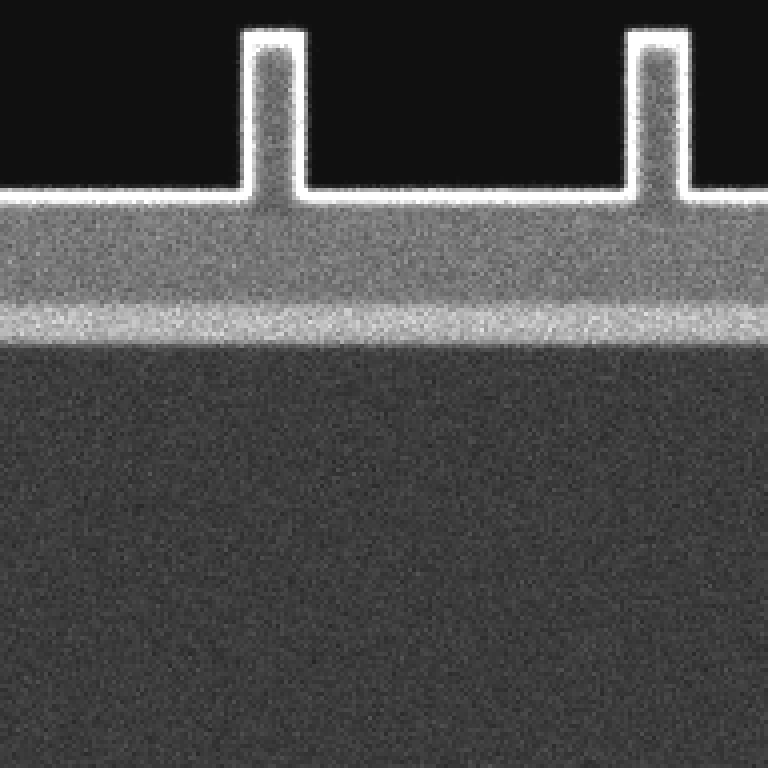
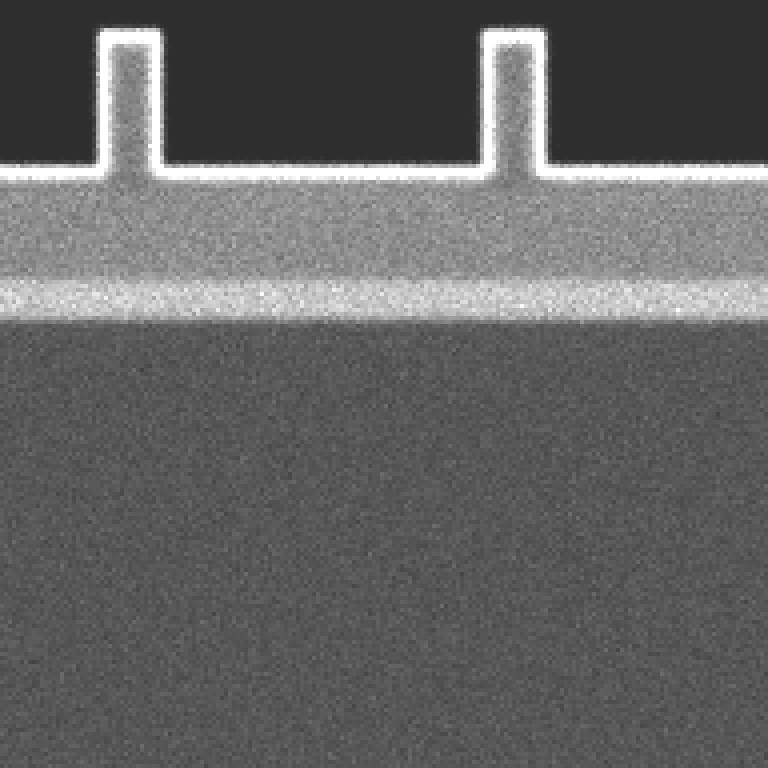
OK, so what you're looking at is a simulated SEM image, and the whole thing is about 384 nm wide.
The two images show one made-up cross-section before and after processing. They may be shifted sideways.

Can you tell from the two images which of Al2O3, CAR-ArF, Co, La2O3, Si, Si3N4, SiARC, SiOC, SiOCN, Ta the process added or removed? Yes, it removed SiARC.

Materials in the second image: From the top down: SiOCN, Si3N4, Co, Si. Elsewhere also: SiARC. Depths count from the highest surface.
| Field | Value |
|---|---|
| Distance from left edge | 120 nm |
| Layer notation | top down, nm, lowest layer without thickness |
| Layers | empty 68, SiOCN 12, Si3N4 44, Co 20, Si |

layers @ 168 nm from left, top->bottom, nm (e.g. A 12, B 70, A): empty 68, SiOCN 12, Si3N4 44, Co 20, Si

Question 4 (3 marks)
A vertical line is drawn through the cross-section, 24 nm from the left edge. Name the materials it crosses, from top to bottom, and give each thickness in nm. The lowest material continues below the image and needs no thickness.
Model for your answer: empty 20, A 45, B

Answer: empty 68, SiOCN 12, Si3N4 44, Co 20, Si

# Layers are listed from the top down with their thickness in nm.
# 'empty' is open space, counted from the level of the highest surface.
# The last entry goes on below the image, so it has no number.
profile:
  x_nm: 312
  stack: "empty 68, SiOCN 12, Si3N4 44, Co 20, Si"